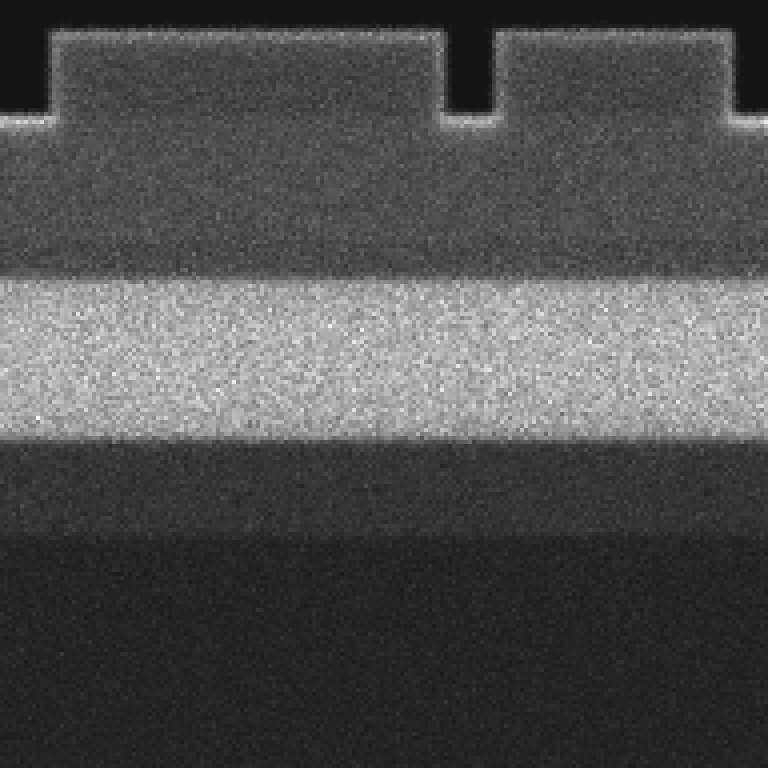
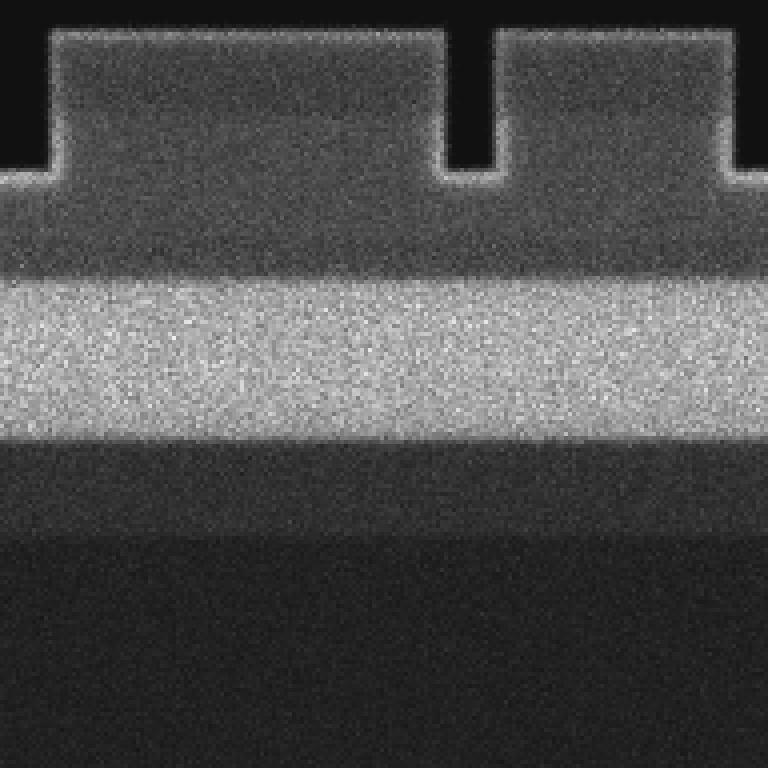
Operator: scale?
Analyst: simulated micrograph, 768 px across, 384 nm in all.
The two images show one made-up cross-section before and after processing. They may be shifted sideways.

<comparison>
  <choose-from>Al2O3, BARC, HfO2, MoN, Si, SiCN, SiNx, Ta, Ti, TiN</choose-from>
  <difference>Al2O3 removed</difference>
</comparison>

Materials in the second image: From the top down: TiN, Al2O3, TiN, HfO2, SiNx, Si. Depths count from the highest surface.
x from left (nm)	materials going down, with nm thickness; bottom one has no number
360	TiN 42, Al2O3 62, TiN 20, HfO2 80, SiNx 48, Si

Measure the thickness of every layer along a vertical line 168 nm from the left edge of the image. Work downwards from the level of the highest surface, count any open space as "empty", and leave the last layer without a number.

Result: TiN 42, Al2O3 62, TiN 20, HfO2 80, SiNx 48, Si